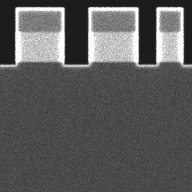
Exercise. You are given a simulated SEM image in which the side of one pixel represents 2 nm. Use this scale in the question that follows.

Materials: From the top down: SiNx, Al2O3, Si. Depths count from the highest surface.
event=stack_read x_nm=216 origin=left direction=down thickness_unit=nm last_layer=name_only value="SiNx 48, Al2O3 60, Si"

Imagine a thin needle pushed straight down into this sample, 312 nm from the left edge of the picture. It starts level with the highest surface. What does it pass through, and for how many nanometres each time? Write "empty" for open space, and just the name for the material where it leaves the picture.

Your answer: empty 114, Si